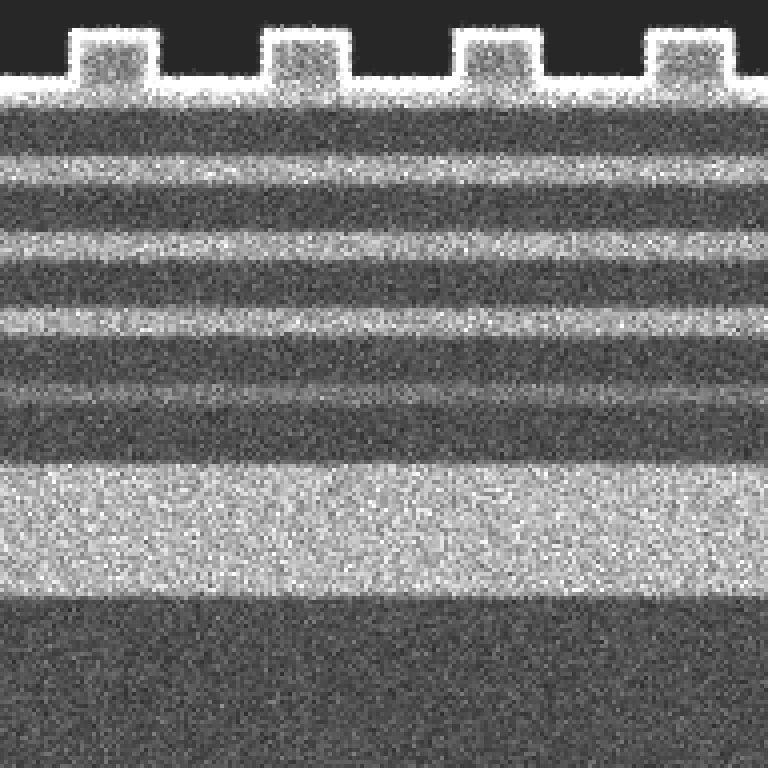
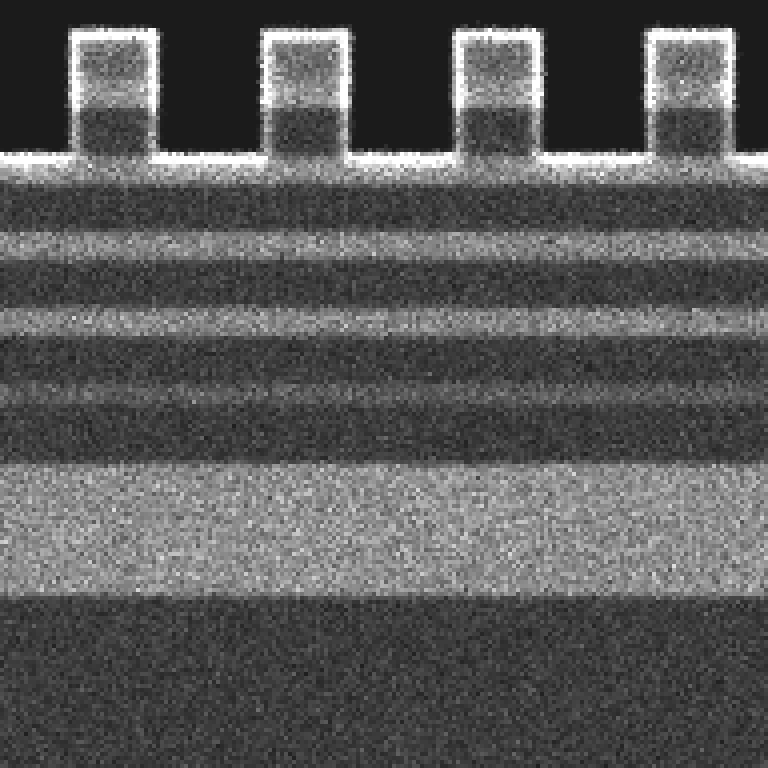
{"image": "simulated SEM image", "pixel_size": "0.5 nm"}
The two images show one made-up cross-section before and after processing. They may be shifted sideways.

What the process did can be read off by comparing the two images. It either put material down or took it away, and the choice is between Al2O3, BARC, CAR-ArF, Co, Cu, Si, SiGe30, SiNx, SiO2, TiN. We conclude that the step removed Co and Si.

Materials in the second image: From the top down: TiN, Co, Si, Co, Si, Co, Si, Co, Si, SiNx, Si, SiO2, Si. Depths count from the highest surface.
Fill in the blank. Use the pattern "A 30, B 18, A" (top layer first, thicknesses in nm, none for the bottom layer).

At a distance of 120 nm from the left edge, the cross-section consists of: empty 62, Co 14, Si 24, Co 14, Si 24, Co 14, Si 24, SiNx 10, Si 30, SiO2 66, Si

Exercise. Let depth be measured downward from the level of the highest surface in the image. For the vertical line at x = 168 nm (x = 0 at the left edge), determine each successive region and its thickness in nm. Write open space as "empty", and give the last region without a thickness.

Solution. TiN 24, Co 14, Si 24, Co 14, Si 24, Co 14, Si 24, Co 14, Si 24, SiNx 10, Si 30, SiO2 66, Si